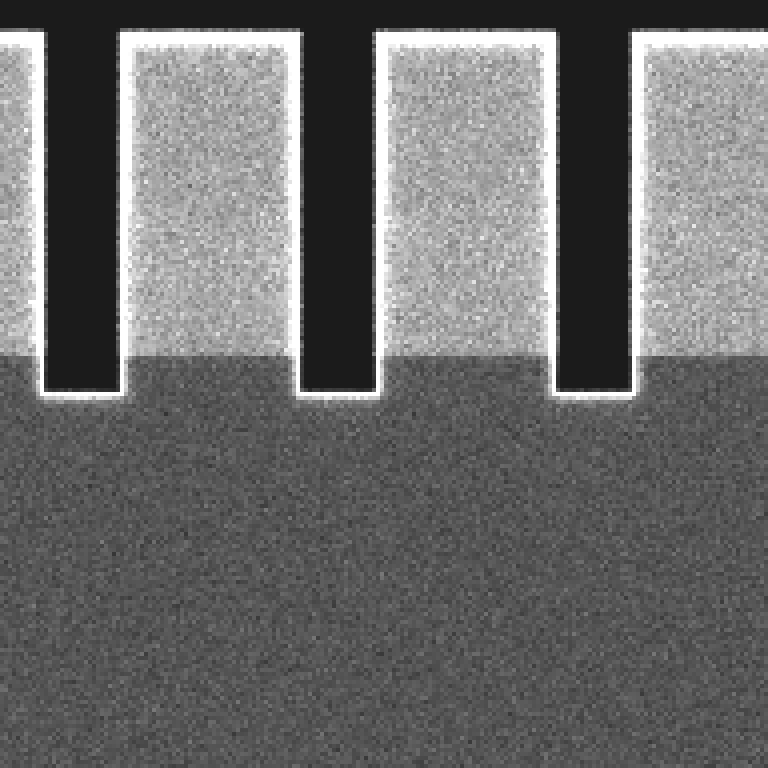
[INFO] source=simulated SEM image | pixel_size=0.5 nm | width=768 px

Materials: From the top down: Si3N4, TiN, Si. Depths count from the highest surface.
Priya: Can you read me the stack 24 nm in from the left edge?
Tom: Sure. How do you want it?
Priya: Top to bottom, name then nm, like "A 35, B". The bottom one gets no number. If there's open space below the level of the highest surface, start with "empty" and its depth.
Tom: empty 180, Si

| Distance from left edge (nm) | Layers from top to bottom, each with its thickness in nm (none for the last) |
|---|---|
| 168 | empty 180, Si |